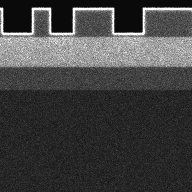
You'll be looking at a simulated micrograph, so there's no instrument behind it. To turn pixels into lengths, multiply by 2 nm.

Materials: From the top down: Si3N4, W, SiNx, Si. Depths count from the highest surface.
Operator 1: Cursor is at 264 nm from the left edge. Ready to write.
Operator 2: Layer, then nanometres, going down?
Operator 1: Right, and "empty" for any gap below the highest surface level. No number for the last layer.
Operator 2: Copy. empty 50, Si3N4 8, W 60, SiNx 46, Si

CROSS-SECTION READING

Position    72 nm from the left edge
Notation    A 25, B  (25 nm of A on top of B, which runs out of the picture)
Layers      Si3N4 58, W 60, SiNx 46, Si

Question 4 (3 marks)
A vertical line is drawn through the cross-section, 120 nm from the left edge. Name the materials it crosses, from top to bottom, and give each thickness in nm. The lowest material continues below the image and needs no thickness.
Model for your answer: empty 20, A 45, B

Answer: empty 50, Si3N4 8, W 60, SiNx 46, Si